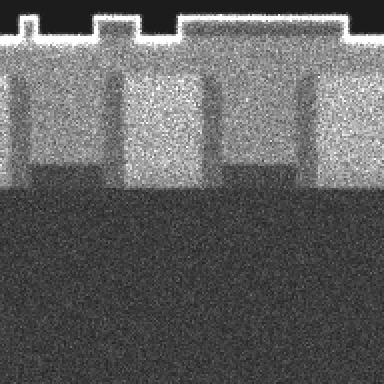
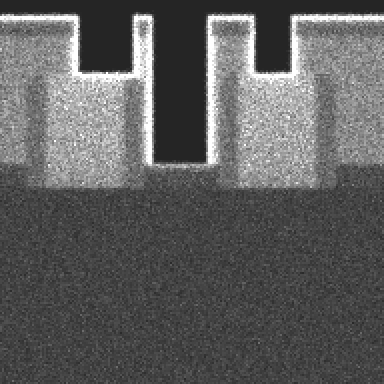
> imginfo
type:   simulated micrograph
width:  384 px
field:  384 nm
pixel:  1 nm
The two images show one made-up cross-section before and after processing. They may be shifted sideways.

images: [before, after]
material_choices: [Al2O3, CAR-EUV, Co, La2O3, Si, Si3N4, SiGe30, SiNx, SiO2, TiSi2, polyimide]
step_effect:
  removed: SiO2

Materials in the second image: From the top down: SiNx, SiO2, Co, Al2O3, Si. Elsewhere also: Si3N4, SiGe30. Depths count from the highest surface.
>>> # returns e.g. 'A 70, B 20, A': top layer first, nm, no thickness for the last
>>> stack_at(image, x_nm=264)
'empty 58, Co 102, Al2O3 12, Si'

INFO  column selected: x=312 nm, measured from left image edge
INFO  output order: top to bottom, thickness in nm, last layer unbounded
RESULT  SiNx 20, SiO2 38, Co 102, Al2O3 12, Si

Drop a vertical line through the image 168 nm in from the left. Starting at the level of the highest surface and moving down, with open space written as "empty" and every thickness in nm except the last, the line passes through empty 148, SiGe30 24, Si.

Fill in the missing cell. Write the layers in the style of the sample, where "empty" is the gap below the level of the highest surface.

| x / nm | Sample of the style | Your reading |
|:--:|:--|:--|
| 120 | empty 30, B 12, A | empty 58, Co 102, Al2O3 12, Si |